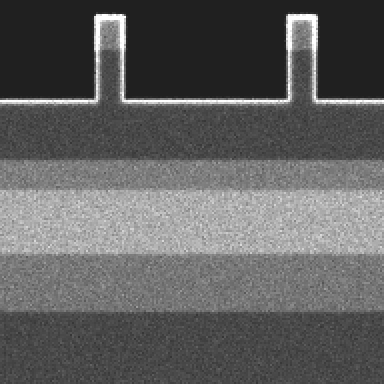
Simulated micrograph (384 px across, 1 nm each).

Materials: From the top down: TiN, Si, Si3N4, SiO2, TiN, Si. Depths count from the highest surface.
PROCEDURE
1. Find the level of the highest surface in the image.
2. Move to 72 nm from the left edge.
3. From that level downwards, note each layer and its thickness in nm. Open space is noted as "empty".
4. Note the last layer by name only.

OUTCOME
empty 84, Si 60, Si3N4 30, SiO2 64, TiN 58, Si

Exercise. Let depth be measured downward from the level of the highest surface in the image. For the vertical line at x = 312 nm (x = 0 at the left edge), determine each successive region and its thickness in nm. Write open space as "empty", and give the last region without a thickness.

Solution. TiN 34, Si 110, Si3N4 30, SiO2 64, TiN 58, Si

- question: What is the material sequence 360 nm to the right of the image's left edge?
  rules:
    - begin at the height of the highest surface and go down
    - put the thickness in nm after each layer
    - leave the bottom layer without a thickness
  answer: empty 84, Si 60, Si3N4 30, SiO2 64, TiN 58, Si